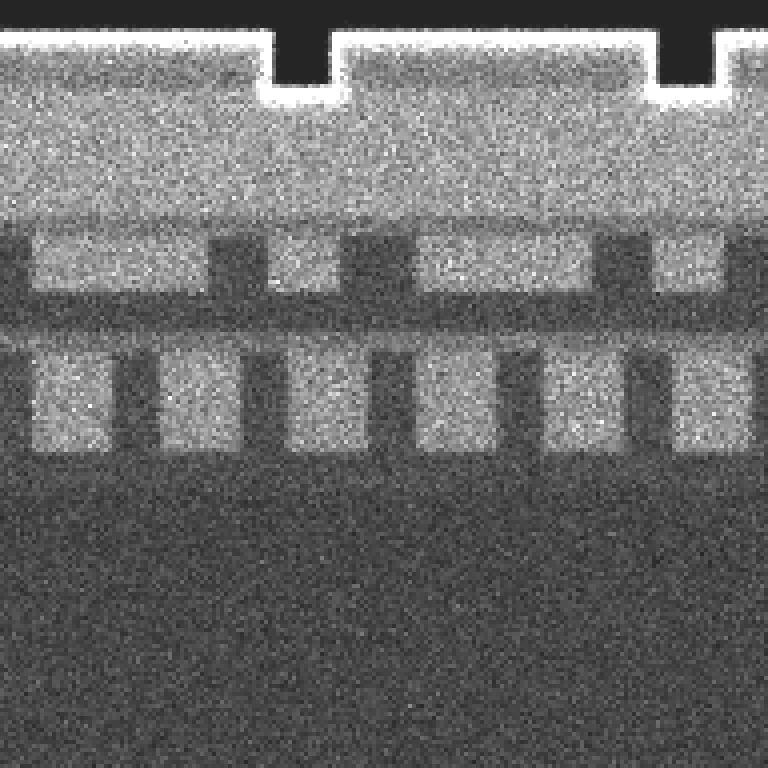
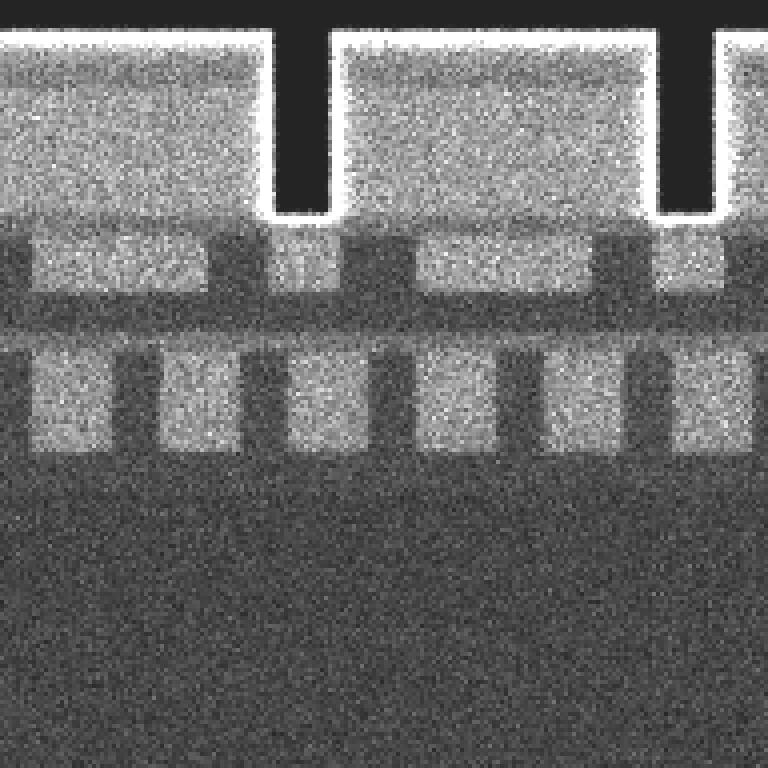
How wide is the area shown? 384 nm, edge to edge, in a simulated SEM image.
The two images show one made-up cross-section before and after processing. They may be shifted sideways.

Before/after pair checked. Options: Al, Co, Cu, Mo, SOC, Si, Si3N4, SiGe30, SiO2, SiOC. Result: removed SiO2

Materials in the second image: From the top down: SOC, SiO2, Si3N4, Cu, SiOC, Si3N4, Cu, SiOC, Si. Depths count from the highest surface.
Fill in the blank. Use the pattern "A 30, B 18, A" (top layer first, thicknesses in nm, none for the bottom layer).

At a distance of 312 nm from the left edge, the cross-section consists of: SOC 28, SiO2 64, Si3N4 10, SiOC 48, Si3N4 10, SiOC 70, Si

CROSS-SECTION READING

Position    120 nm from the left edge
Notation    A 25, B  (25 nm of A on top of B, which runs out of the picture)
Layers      SOC 28, SiO2 64, Si3N4 10, SiOC 48, Si3N4 10, SiOC 70, Si